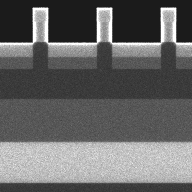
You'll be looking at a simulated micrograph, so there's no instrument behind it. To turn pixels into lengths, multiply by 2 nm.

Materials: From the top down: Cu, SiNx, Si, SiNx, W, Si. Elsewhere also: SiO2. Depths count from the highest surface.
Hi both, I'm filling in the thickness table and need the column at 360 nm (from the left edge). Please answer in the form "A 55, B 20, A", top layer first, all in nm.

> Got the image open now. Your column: empty 70, Cu 28, SiNx 24, Si 60, SiNx 86, W 82, Si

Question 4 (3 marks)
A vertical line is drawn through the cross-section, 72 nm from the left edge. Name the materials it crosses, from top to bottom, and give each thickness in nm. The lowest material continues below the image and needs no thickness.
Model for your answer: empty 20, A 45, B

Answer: Cu 28, SiO2 40, Si 114, SiNx 86, W 82, Si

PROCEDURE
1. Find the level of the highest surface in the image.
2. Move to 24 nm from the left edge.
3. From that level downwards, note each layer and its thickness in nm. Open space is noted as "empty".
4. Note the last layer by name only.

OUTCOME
empty 70, Cu 28, SiNx 24, Si 60, SiNx 86, W 82, Si